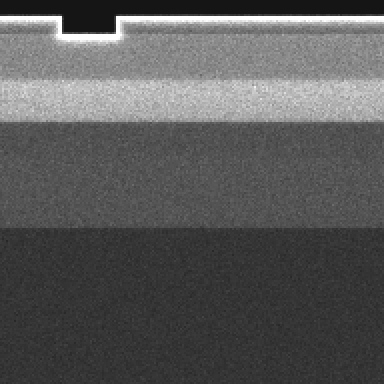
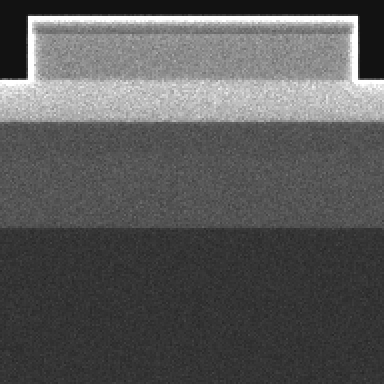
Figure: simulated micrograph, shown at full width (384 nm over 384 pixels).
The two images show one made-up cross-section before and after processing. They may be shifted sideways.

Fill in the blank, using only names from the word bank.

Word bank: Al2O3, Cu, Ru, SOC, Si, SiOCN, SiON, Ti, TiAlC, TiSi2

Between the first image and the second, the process removed Al2O3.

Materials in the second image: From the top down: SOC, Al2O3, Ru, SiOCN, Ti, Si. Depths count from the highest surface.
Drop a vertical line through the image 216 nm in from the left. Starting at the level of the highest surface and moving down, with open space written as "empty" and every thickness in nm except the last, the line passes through SOC 18, Al2O3 46, Ru 42, SiOCN 34, Ti 72, Si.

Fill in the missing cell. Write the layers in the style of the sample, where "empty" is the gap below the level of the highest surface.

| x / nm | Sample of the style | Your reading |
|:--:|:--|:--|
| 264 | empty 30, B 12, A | SOC 18, Al2O3 46, Ru 42, SiOCN 34, Ti 72, Si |